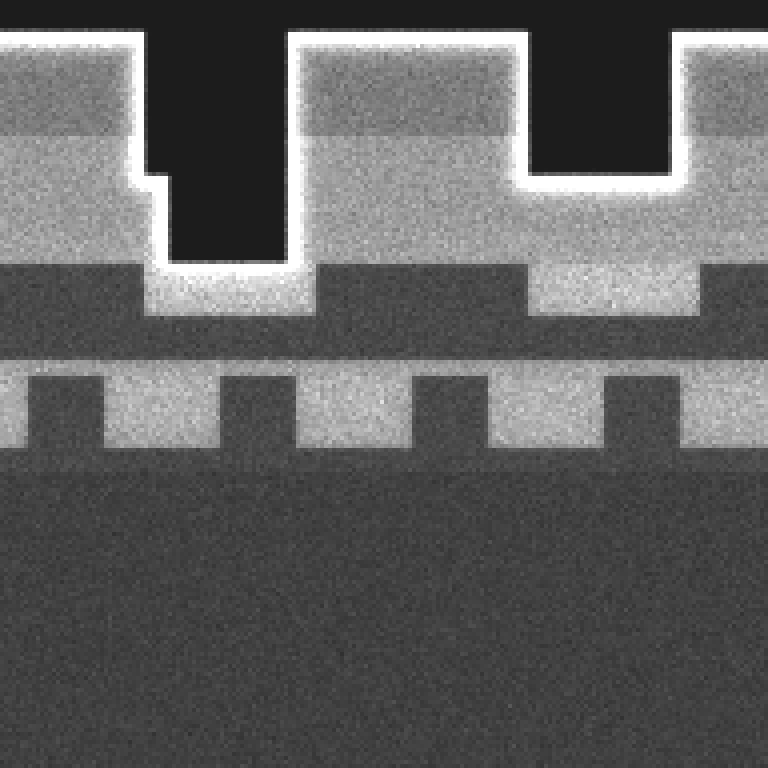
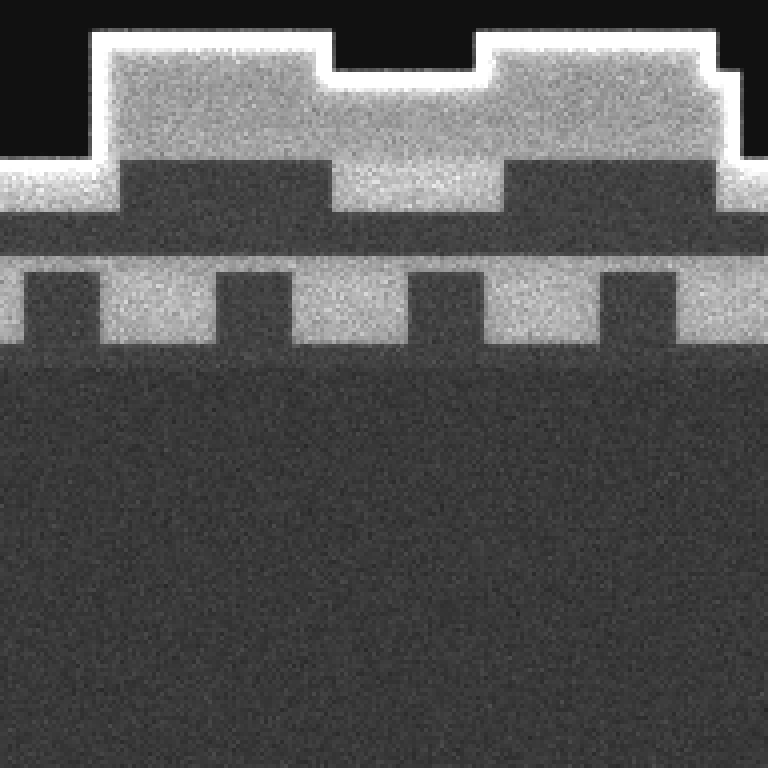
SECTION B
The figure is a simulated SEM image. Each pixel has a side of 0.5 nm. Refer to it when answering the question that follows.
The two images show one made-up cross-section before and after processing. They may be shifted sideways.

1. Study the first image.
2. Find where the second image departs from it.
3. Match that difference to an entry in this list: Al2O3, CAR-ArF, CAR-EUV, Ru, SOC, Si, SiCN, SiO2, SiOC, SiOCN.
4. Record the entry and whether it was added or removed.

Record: SOC / removed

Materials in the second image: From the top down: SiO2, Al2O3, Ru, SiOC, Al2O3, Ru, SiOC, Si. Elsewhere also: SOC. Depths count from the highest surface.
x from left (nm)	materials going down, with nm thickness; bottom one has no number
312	SiO2 48, Al2O3 16, SiOC 48, Al2O3 8, SiOC 48, Si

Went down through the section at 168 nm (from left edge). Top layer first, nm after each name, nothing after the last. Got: empty 20, SiO2 28, Al2O3 16, Ru 26, SiOC 22, Al2O3 8, Ru 36, SiOC 12, Si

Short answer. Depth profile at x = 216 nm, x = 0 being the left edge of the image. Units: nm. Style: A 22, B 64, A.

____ empty 20, SiO2 28, Al2O3 16, Ru 26, SiOC 22, Al2O3 8, SiOC 48, Si